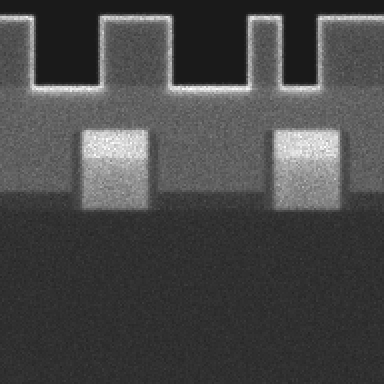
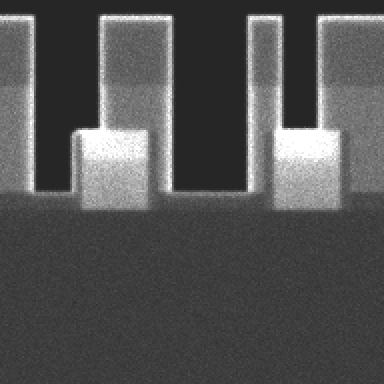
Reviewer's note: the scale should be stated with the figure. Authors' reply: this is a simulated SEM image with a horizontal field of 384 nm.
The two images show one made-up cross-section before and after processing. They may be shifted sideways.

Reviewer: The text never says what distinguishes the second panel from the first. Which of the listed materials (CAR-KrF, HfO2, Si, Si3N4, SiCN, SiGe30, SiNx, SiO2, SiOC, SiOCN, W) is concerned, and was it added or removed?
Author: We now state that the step removed SiO2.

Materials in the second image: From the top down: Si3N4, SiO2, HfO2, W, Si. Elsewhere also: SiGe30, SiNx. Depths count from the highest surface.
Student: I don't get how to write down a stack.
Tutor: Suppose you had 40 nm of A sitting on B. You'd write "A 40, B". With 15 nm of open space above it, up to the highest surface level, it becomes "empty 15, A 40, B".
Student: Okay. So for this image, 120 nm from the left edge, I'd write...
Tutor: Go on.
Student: Si3N4 70, SiO2 44, HfO2 28, W 52, Si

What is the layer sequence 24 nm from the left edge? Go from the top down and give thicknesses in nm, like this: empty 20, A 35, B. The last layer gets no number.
Si3N4 70, SiO2 106, SiGe30 18, Si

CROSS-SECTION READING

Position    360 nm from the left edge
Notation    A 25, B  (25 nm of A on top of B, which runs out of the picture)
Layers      Si3N4 70, SiO2 106, SiGe30 18, Si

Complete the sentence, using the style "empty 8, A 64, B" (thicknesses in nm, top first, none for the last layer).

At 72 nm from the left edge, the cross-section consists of empty 118, SiNx 76, Si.